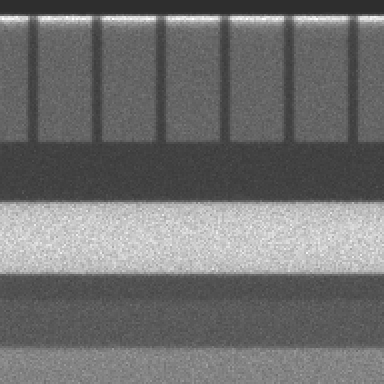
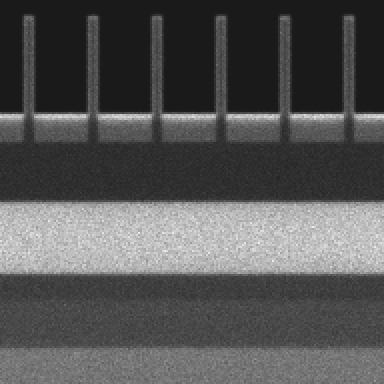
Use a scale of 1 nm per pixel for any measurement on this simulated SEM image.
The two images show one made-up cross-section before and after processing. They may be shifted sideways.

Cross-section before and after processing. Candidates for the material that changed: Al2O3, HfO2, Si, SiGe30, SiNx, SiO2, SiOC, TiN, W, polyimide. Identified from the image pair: SiO2 (removed).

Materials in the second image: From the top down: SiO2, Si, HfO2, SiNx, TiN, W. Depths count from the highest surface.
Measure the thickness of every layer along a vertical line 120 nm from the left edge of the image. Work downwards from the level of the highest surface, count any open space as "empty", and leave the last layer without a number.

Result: empty 98, SiO2 28, Si 60, HfO2 72, SiNx 26, TiN 48, W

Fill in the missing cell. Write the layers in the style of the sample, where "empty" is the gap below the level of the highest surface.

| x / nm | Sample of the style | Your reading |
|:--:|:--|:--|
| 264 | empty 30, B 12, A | empty 98, SiO2 28, Si 60, HfO2 72, SiNx 26, TiN 48, W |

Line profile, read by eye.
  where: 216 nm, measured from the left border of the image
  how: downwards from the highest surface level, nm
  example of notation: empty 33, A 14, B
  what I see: Si 186, HfO2 72, SiNx 26, TiN 48, W